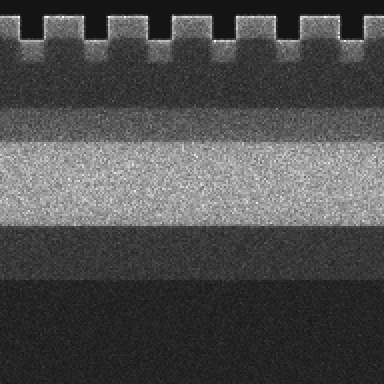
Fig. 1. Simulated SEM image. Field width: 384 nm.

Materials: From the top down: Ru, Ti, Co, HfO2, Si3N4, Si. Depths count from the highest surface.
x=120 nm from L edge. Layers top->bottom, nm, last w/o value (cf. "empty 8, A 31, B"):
Ru 22, Ti 70, Co 34, HfO2 84, Si3N4 54, Si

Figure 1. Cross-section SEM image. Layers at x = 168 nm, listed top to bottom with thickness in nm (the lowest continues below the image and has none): empty 24, Ru 22, Ti 46, Co 34, HfO2 84, Si3N4 54, Si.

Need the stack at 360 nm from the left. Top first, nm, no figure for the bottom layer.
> empty 24, Ru 22, Ti 46, Co 34, HfO2 84, Si3N4 54, Si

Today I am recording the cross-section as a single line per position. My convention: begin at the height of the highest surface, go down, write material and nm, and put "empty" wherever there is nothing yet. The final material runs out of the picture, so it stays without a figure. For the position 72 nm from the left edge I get Ru 22, Ti 70, Co 34, HfO2 84, Si3N4 54, Si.